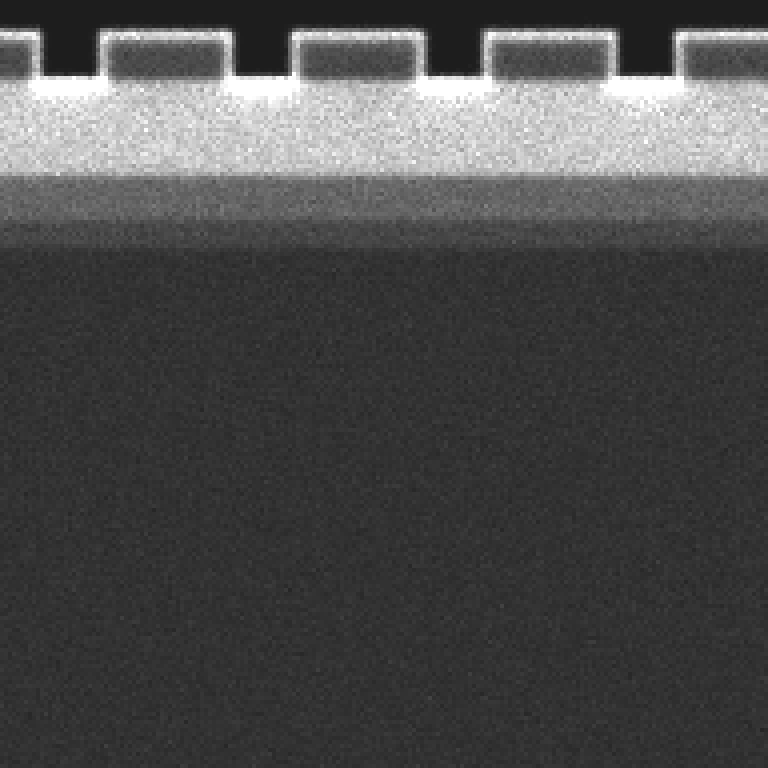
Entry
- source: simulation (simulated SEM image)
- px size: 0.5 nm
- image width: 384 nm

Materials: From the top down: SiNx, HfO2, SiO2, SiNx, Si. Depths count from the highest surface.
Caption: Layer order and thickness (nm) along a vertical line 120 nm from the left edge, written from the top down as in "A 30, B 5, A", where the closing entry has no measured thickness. empty 24, HfO2 48, SiO2 22, SiNx 14, Si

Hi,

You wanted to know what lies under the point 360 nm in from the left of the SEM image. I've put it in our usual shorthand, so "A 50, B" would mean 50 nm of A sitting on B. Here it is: SiNx 24, HfO2 48, SiO2 22, SiNx 14, Si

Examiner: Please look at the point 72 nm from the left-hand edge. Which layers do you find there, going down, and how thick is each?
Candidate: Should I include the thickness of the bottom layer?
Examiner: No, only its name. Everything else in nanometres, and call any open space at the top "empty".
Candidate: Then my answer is SiNx 24, HfO2 48, SiO2 22, SiNx 14, Si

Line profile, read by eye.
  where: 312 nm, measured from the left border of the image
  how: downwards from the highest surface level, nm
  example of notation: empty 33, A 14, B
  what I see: empty 24, HfO2 48, SiO2 22, SiNx 14, Si